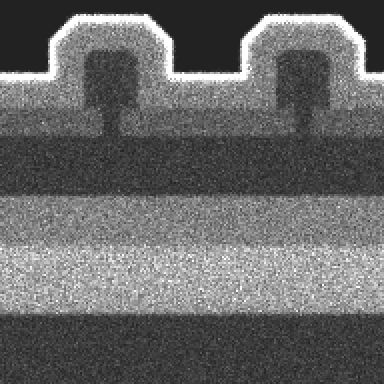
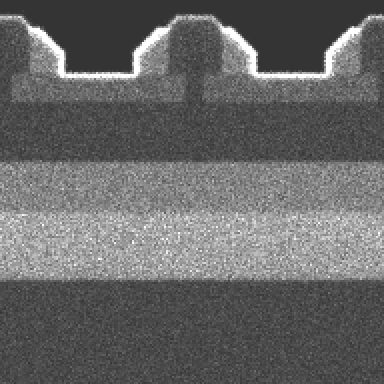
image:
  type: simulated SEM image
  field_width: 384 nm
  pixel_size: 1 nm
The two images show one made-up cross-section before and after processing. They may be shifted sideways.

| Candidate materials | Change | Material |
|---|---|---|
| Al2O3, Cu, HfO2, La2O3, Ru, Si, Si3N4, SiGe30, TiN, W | removed | Al2O3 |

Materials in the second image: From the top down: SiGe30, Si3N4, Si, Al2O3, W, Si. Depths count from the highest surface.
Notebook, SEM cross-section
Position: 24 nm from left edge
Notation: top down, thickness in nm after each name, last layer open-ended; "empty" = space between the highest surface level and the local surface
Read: empty 4, SiGe30 54, Si3N4 28, Si 60, Al2O3 50, W 68, Si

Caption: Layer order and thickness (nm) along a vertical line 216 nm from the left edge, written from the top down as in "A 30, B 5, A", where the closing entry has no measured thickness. empty 4, SiGe30 54, Si3N4 28, Si 60, Al2O3 50, W 68, Si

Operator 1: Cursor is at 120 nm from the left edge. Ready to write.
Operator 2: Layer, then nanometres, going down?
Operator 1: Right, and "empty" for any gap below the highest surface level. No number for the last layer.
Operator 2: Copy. empty 58, Si3N4 28, Si 60, Al2O3 50, W 68, Si